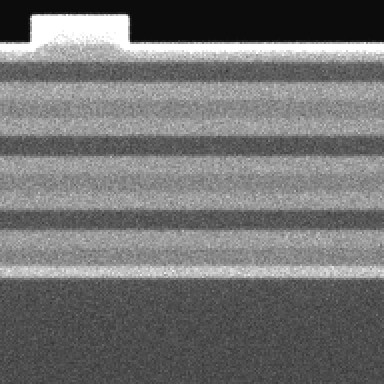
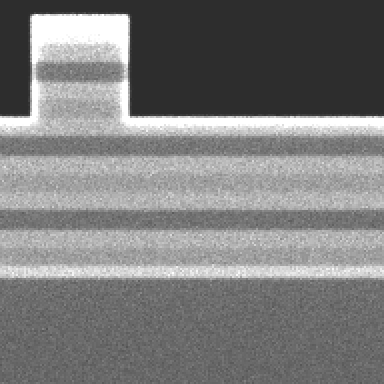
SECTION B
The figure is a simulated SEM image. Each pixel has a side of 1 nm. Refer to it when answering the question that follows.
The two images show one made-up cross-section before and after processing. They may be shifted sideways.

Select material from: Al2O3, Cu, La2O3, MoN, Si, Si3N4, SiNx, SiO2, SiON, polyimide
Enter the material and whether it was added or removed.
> Si and Si3N4 and SiNx / removed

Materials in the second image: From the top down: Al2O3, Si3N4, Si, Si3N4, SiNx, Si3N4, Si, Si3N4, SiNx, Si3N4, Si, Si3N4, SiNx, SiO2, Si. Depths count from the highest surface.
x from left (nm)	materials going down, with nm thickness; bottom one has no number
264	empty 102, Si3N4 18, Si 20, Si3N4 18, SiNx 18, Si3N4 18, Si 20, Si3N4 18, SiNx 18, SiO2 12, Si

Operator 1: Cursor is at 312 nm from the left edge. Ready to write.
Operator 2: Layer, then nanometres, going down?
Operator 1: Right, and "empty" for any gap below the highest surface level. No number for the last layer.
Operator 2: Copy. empty 102, Si3N4 18, Si 20, Si3N4 18, SiNx 18, Si3N4 18, Si 20, Si3N4 18, SiNx 18, SiO2 12, Si